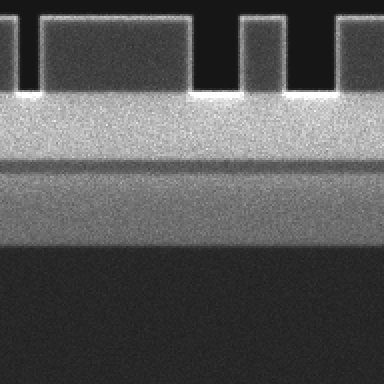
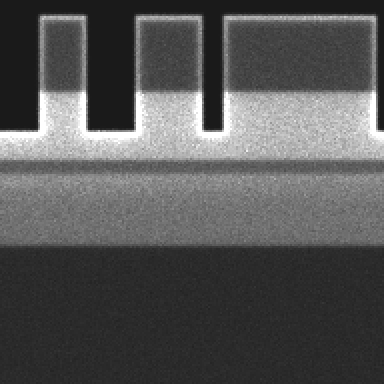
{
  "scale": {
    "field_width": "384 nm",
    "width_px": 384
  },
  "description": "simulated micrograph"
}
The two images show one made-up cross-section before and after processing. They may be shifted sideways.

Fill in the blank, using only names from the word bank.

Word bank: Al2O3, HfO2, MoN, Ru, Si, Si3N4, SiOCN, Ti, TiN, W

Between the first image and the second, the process removed HfO2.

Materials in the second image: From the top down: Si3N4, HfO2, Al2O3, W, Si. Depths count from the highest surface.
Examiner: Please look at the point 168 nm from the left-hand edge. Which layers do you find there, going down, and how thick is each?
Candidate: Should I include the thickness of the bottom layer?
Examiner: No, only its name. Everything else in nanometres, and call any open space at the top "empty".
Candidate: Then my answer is Si3N4 76, HfO2 68, Al2O3 14, W 72, Si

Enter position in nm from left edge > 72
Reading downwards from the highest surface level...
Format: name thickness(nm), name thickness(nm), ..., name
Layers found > Si3N4 76, HfO2 68, Al2O3 14, W 72, Si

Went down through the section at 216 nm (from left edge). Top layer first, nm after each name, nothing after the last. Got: empty 116, HfO2 28, Al2O3 14, W 72, Si